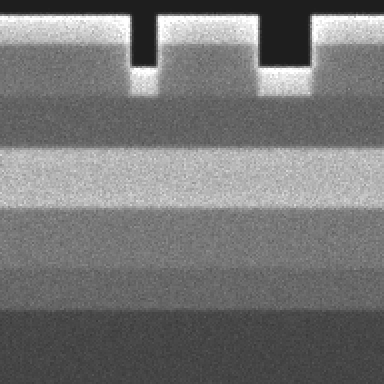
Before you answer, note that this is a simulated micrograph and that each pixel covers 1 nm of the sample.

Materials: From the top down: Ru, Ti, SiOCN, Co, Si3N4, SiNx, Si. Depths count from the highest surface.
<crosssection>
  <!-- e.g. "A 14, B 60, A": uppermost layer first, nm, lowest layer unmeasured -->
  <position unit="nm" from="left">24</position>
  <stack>Ru 28, Ti 52, SiOCN 52, Co 60, Si3N4 60, SiNx 42, Si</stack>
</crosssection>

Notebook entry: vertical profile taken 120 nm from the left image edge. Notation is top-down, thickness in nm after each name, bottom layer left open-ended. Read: Ru 28, Ti 52, SiOCN 52, Co 60, Si3N4 60, SiNx 42, Si